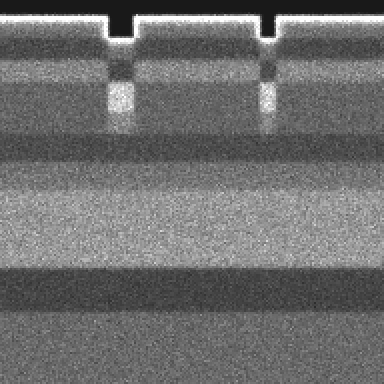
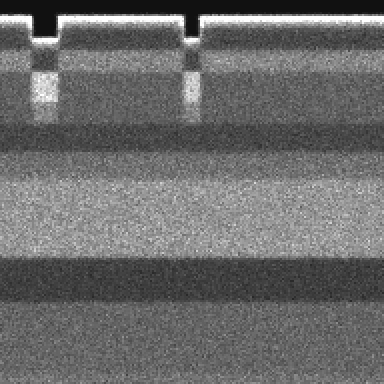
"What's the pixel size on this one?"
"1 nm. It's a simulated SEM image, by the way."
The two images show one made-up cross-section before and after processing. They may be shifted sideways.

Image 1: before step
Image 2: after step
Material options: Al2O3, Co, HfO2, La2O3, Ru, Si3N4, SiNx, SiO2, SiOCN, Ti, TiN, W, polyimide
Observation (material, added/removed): Al2O3, removed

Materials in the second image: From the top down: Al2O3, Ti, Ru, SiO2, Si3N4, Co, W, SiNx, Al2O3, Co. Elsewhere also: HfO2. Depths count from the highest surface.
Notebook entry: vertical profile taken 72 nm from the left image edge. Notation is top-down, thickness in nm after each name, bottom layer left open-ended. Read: Al2O3 12, Ti 22, Ru 22, SiO2 52, Si3N4 28, Co 28, W 78, SiNx 44, Al2O3 72, Co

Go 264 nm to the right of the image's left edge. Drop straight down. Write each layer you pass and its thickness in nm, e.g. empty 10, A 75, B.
Al2O3 12, Ti 22, Ru 22, SiO2 52, Si3N4 28, Co 28, W 78, SiNx 44, Al2O3 72, Co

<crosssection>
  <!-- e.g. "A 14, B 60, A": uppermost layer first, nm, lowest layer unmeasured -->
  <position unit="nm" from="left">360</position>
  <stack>Al2O3 12, Ti 22, Ru 22, SiO2 52, Si3N4 28, Co 28, W 78, SiNx 44, Al2O3 72, Co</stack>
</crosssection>